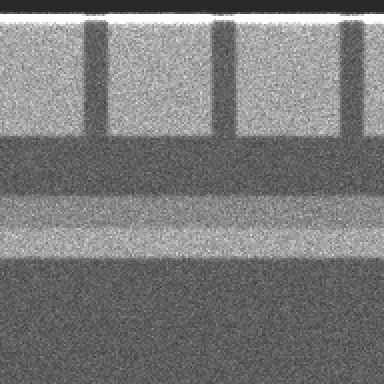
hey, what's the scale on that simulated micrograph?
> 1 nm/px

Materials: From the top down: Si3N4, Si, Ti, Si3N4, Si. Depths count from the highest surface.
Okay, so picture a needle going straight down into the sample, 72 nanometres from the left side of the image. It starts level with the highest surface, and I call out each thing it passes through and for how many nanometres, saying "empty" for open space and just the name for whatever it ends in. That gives Si3N4 120, Si 60, Ti 32, Si3N4 30, Si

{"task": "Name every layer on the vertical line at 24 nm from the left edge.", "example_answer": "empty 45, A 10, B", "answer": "Si3N4 120, Si 60, Ti 32, Si3N4 30, Si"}